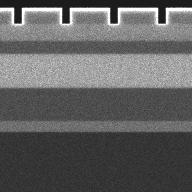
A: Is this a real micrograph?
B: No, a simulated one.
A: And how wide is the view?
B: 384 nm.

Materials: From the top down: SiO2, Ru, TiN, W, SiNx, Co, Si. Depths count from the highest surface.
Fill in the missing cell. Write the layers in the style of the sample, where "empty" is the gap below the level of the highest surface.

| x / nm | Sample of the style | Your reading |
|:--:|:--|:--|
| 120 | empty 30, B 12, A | SiO2 32, Ru 34, TiN 26, W 68, SiNx 66, Co 22, Si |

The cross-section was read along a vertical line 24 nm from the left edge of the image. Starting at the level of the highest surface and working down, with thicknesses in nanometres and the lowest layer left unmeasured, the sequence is SiO2 32, Ru 34, TiN 26, W 68, SiNx 66, Co 22, Si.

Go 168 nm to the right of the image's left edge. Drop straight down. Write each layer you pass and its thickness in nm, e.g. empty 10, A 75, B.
SiO2 32, Ru 34, TiN 26, W 68, SiNx 66, Co 22, Si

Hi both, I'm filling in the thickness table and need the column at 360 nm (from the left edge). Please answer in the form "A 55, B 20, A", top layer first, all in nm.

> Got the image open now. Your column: SiO2 32, Ru 34, TiN 26, W 68, SiNx 66, Co 22, Si